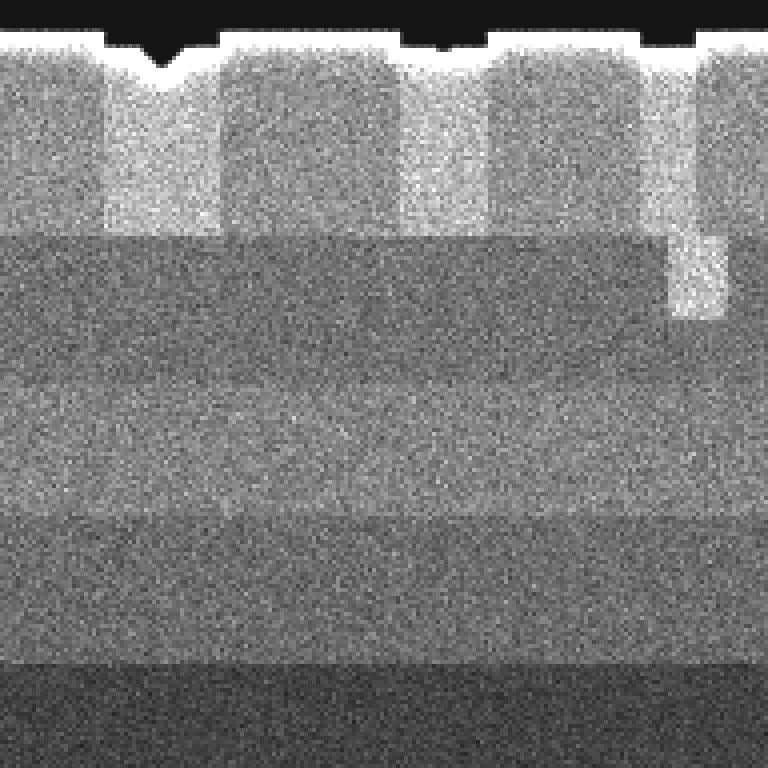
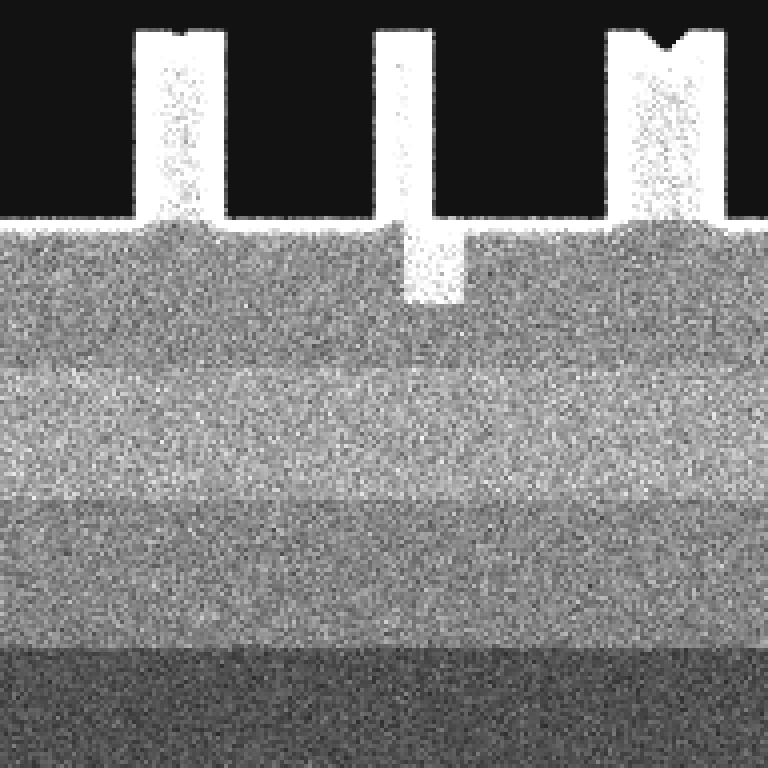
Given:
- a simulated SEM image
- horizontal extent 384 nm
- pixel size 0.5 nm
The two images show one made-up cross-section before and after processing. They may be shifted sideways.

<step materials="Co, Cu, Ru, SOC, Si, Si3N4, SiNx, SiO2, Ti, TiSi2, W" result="removed SOC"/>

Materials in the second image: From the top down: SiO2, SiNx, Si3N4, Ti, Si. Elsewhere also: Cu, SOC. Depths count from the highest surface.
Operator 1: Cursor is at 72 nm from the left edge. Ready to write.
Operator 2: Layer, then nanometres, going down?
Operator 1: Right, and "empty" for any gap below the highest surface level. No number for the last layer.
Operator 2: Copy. SiO2 94, SiNx 74, Si3N4 66, Ti 74, Si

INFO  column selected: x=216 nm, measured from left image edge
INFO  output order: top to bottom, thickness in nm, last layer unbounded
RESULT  empty 94, Cu 42, SiNx 32, Si3N4 66, Ti 74, Si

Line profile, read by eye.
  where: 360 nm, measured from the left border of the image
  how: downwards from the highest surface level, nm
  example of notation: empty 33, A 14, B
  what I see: SiO2 94, SiNx 74, Si3N4 66, Ti 74, Si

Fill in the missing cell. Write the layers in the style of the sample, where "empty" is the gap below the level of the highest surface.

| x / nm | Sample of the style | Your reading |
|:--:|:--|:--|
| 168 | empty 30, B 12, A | empty 94, SiNx 74, Si3N4 66, Ti 74, Si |